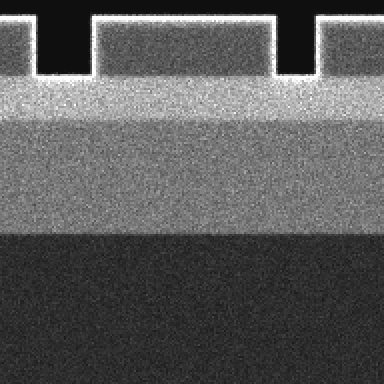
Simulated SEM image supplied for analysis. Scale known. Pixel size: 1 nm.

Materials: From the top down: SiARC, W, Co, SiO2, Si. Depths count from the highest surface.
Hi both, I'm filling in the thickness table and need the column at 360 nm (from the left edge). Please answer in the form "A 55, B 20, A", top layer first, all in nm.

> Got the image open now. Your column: SiARC 60, W 44, Co 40, SiO2 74, Si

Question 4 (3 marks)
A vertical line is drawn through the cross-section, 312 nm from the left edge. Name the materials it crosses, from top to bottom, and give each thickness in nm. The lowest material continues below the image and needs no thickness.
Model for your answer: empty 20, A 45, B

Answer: empty 60, W 44, Co 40, SiO2 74, Si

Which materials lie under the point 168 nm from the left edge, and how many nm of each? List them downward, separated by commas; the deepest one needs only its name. SiARC 60, W 44, Co 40, SiO2 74, Si